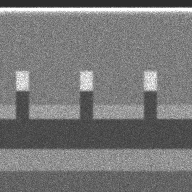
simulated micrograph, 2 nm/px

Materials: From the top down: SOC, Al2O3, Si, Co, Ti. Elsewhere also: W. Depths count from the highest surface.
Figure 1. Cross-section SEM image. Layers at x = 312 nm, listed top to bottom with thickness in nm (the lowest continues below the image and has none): SOC 126, W 40, Si 116, Co 44, Ti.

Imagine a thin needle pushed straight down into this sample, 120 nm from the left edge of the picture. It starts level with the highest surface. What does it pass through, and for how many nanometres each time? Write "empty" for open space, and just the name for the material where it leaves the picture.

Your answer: SOC 194, Al2O3 28, Si 60, Co 44, Ti